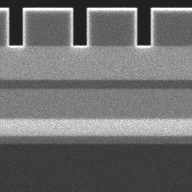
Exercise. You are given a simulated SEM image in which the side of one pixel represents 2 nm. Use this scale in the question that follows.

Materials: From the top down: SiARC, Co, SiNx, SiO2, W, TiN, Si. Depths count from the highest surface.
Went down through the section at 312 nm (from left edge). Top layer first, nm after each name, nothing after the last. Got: SiARC 76, Co 68, SiNx 18, SiO2 60, W 34, TiN 16, Si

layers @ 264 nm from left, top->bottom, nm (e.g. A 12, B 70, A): SiARC 76, Co 68, SiNx 18, SiO2 60, W 34, TiN 16, Si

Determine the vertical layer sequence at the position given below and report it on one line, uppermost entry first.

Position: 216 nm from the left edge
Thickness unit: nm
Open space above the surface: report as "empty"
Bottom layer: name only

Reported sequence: SiARC 76, Co 68, SiNx 18, SiO2 60, W 34, TiN 16, Si